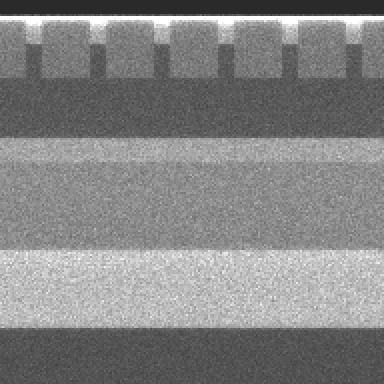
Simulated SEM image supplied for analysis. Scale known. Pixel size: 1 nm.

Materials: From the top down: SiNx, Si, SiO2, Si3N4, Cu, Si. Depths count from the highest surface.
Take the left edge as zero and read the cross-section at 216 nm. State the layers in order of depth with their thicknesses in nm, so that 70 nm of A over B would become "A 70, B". SiNx 62, Si 60, SiO2 24, Si3N4 88, Cu 78, Si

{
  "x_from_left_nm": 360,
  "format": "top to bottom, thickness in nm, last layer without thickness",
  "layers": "SiO2 28, Si 94, SiO2 24, Si3N4 88, Cu 78, Si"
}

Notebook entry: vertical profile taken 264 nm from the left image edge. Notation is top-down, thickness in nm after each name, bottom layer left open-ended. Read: SiNx 62, Si 60, SiO2 24, Si3N4 88, Cu 78, Si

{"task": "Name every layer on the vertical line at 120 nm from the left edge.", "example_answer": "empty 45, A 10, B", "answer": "SiNx 62, Si 60, SiO2 24, Si3N4 88, Cu 78, Si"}